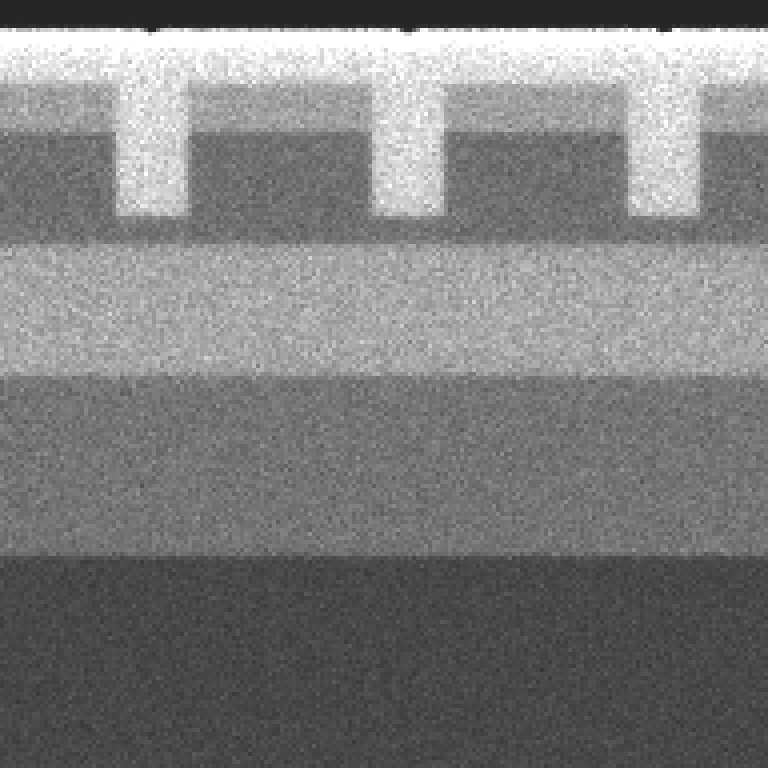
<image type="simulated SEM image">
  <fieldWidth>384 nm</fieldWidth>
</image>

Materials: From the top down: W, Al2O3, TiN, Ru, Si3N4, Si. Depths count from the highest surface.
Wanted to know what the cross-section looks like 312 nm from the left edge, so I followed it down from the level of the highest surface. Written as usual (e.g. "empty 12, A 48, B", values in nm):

W 26, Al2O3 24, TiN 56, Ru 66, Si3N4 90, Si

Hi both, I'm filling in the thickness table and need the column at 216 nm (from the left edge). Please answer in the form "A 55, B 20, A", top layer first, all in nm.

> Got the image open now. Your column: W 92, TiN 14, Ru 66, Si3N4 90, Si